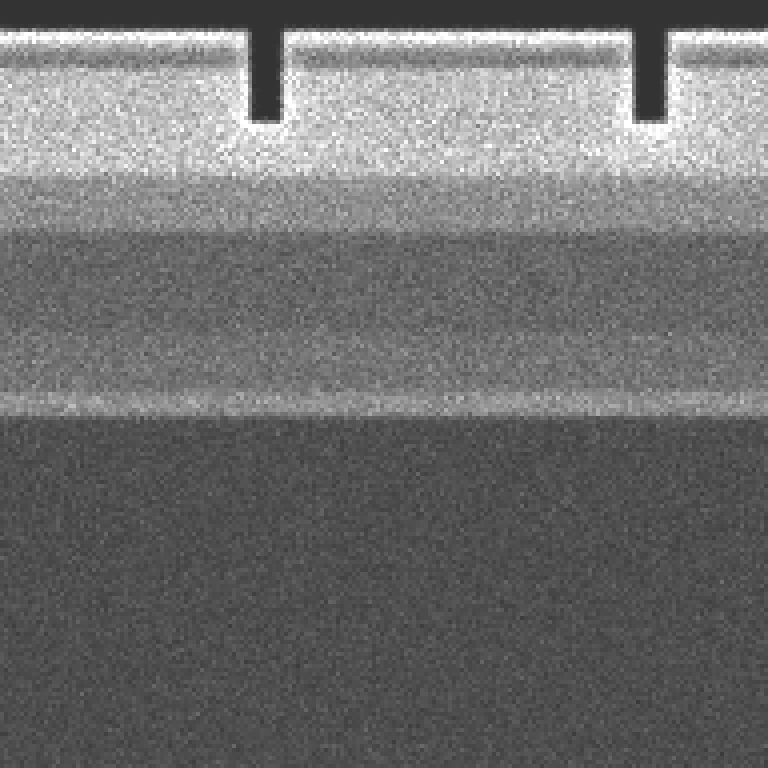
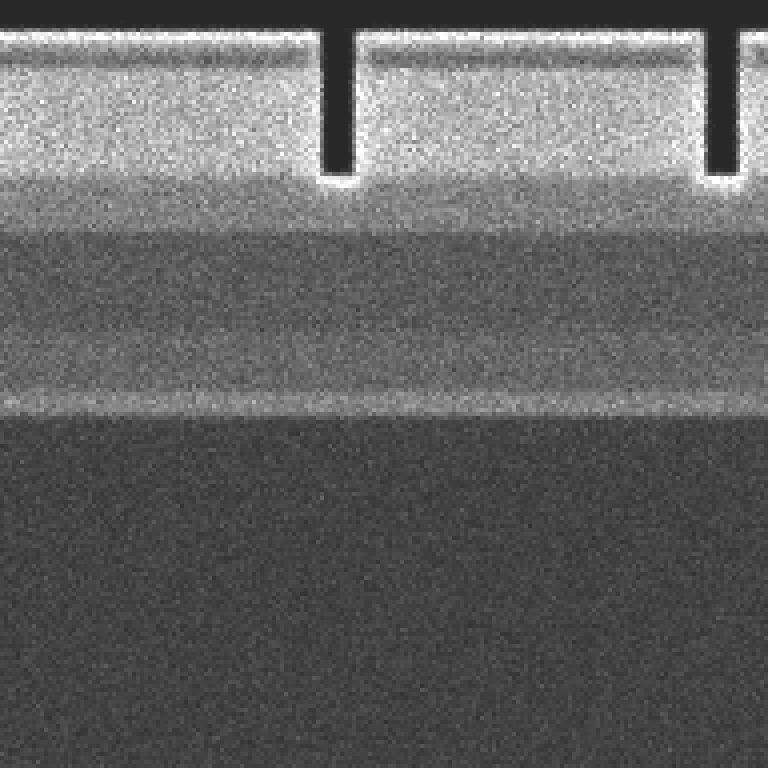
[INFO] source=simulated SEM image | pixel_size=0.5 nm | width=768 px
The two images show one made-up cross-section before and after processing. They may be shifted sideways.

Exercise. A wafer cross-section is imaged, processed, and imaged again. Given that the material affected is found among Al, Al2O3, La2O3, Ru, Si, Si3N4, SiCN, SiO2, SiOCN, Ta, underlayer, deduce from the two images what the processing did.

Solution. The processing removed Ru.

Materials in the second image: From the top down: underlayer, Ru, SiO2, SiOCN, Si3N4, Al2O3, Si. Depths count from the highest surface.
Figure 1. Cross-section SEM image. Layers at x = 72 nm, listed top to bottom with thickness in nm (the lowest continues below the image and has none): underlayer 18, Ru 54, SiO2 28, SiOCN 50, Si3N4 30, Al2O3 12, Si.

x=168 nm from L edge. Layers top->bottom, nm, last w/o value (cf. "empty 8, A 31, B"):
empty 72, SiO2 28, SiOCN 50, Si3N4 30, Al2O3 12, Si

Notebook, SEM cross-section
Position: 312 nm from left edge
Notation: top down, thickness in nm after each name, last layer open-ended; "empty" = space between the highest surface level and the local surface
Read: underlayer 18, Ru 54, SiO2 28, SiOCN 50, Si3N4 30, Al2O3 12, Si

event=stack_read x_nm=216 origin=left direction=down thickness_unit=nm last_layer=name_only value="underlayer 18, Ru 54, SiO2 28, SiOCN 50, Si3N4 30, Al2O3 12, Si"